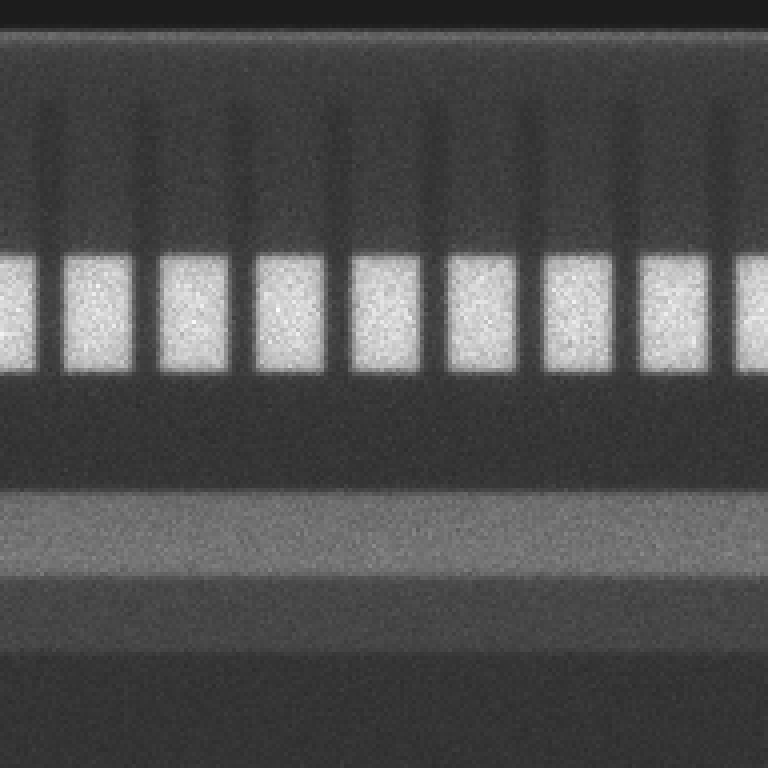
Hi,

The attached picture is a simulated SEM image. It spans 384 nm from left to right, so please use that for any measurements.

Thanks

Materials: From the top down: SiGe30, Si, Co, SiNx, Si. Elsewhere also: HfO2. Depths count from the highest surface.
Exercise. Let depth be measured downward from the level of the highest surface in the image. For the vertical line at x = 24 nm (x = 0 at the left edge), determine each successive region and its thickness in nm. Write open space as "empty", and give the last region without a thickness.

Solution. SiGe30 34, Si 196, Co 42, SiNx 38, Si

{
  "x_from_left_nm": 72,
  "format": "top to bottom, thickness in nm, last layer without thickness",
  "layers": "SiGe30 34, Si 196, Co 42, SiNx 38, Si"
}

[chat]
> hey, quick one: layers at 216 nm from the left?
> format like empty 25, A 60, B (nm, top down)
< SiGe30 34, Si 196, Co 42, SiNx 38, Si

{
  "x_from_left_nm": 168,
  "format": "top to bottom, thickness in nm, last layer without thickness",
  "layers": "SiGe30 34, Si 196, Co 42, SiNx 38, Si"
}